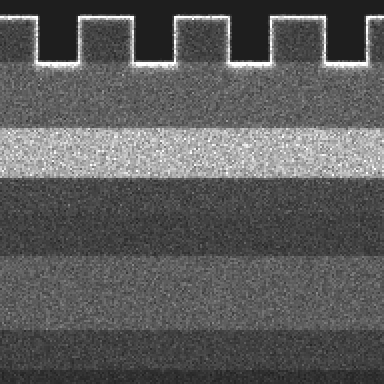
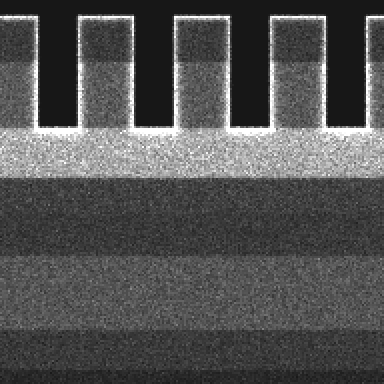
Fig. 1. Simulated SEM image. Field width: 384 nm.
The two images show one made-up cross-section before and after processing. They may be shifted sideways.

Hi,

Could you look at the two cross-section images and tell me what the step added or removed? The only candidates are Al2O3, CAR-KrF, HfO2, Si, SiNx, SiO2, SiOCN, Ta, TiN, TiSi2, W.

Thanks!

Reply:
removed Al2O3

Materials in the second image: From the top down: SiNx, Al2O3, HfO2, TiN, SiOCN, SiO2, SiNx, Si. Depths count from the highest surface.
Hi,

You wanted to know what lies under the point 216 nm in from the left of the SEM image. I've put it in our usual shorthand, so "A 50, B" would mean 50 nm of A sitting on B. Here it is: SiNx 46, Al2O3 66, HfO2 50, TiN 36, SiOCN 42, SiO2 74, SiNx 40, Si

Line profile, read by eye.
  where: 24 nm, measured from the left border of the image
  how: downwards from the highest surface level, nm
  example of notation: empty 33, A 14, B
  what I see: SiNx 46, Al2O3 66, HfO2 50, TiN 36, SiOCN 42, SiO2 74, SiNx 40, Si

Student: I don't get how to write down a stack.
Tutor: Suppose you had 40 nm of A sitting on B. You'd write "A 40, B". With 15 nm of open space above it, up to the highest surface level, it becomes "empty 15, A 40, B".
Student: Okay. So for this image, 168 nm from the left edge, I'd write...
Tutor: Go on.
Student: empty 112, HfO2 50, TiN 36, SiOCN 42, SiO2 74, SiNx 40, Si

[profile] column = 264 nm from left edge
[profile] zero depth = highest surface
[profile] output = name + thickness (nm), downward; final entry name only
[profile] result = empty 112, HfO2 50, TiN 36, SiOCN 42, SiO2 74, SiNx 40, Si